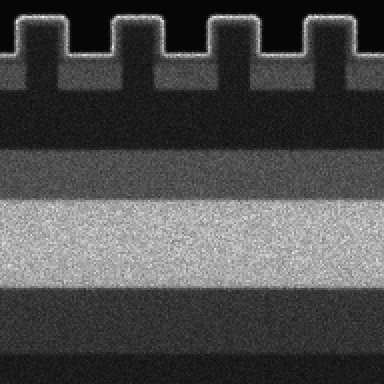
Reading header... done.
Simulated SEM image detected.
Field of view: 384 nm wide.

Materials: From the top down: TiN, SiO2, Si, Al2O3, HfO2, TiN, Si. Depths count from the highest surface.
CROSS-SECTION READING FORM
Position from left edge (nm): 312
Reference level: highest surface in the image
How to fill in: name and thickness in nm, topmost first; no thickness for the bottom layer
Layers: TiN 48, SiO2 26, Si 60, Al2O3 50, HfO2 88, TiN 66, Si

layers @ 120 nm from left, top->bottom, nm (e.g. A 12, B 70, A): TiN 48, SiO2 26, Si 60, Al2O3 50, HfO2 88, TiN 66, Si